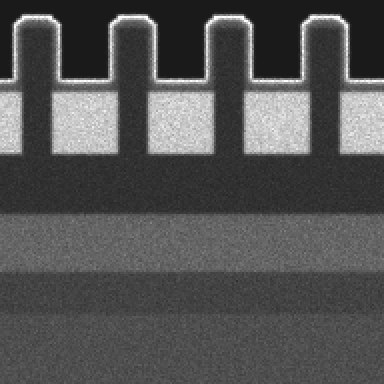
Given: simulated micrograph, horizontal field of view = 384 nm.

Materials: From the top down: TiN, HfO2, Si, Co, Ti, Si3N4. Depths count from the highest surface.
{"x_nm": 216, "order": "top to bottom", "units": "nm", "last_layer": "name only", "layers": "TiN 12, Si 186, Co 58, Ti 42, Si3N4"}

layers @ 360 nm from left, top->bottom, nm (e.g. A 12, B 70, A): empty 64, TiN 12, HfO2 62, Si 60, Co 58, Ti 42, Si3N4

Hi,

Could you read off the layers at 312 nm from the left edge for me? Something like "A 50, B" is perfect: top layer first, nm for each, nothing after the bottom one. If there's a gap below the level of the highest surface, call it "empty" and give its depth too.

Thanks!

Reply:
TiN 12, Si 186, Co 58, Ti 42, Si3N4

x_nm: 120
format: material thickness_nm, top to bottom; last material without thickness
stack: TiN 12, Si 186, Co 58, Ti 42, Si3N4